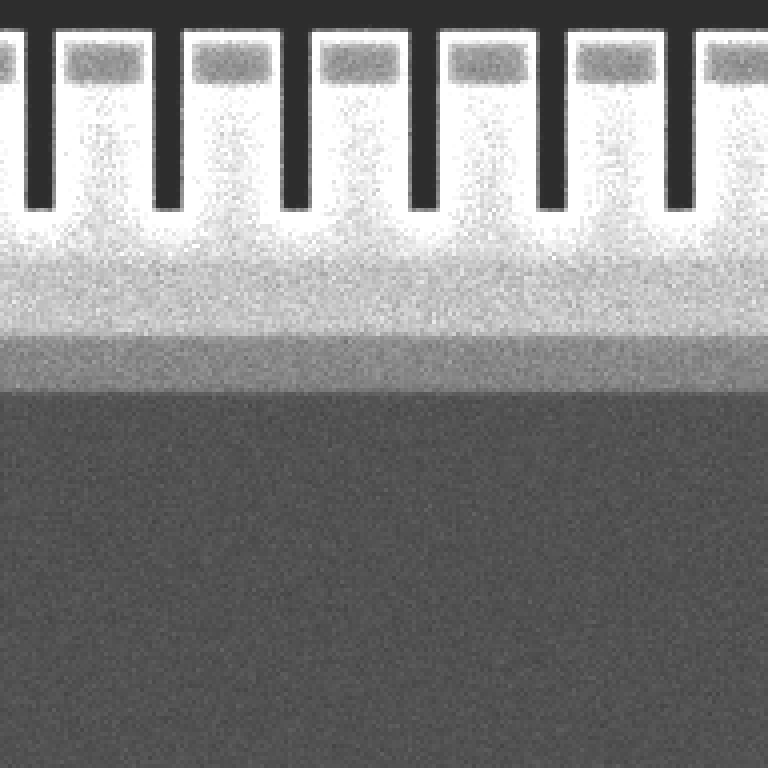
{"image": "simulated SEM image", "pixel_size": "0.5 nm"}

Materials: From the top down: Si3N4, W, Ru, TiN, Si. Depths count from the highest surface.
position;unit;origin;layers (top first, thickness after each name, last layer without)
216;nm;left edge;empty 90, W 24, Ru 38, TiN 28, Si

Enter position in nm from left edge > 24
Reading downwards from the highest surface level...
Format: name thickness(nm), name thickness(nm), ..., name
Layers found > empty 90, W 24, Ru 38, TiN 28, Si